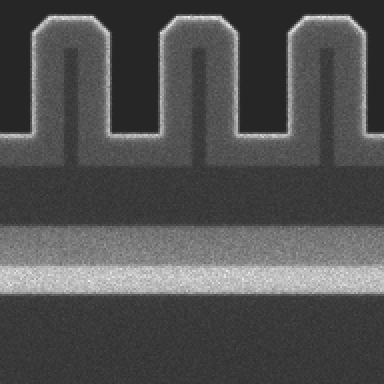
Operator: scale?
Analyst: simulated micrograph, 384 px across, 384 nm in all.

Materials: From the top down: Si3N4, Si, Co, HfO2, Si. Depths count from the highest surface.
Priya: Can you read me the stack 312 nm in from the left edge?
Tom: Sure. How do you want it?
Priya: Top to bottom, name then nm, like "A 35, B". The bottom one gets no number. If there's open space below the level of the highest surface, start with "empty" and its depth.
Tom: Si3N4 150, Si 60, Co 40, HfO2 28, Si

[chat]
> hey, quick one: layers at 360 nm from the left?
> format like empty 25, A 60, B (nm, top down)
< empty 12, Si3N4 138, Si 60, Co 40, HfO2 28, Si